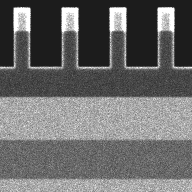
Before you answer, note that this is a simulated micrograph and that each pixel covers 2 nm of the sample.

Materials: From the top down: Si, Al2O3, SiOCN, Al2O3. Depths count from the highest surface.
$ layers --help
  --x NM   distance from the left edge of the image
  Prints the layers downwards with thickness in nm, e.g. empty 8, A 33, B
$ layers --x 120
empty 118, Si 60, Al2O3 86, SiOCN 78, Al2O3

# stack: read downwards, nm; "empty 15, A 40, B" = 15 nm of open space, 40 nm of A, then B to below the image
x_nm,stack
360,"empty 118, Si 60, Al2O3 86, SiOCN 78, Al2O3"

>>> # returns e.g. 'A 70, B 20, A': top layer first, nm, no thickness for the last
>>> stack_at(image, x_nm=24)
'empty 118, Si 60, Al2O3 86, SiOCN 78, Al2O3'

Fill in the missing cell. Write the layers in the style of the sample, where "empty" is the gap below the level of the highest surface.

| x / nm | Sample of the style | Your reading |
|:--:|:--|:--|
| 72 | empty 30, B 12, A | empty 118, Si 60, Al2O3 86, SiOCN 78, Al2O3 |